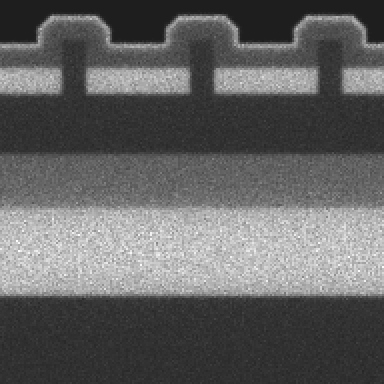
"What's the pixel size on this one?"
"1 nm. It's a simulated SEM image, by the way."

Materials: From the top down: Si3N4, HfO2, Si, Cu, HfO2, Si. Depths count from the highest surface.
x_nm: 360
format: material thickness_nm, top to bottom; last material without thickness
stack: empty 8, Si3N4 44, HfO2 26, Si 60, Cu 54, HfO2 88, Si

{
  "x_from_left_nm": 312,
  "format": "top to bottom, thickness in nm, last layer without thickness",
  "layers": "Si3N4 52, HfO2 26, Si 60, Cu 54, HfO2 88, Si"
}